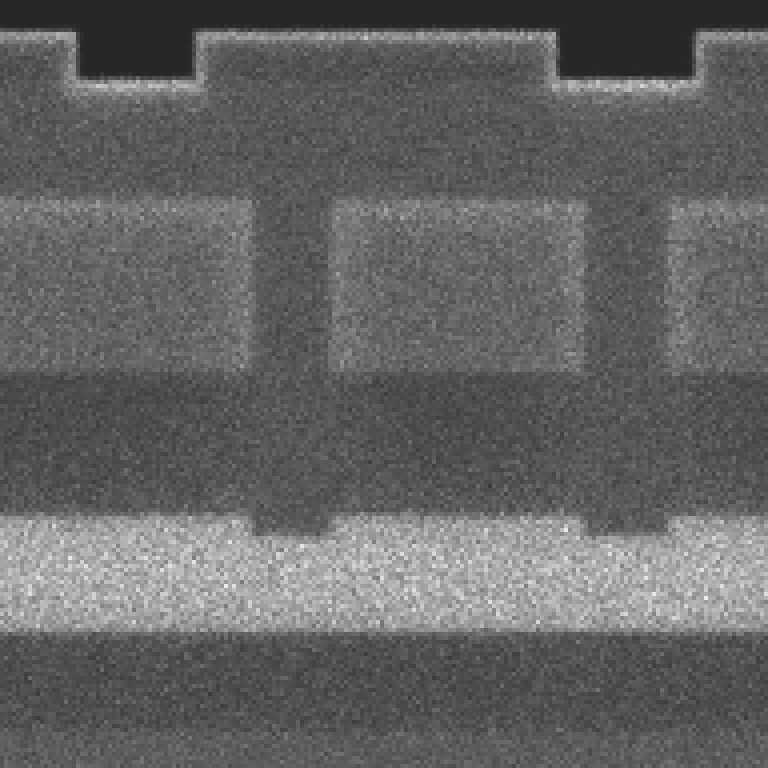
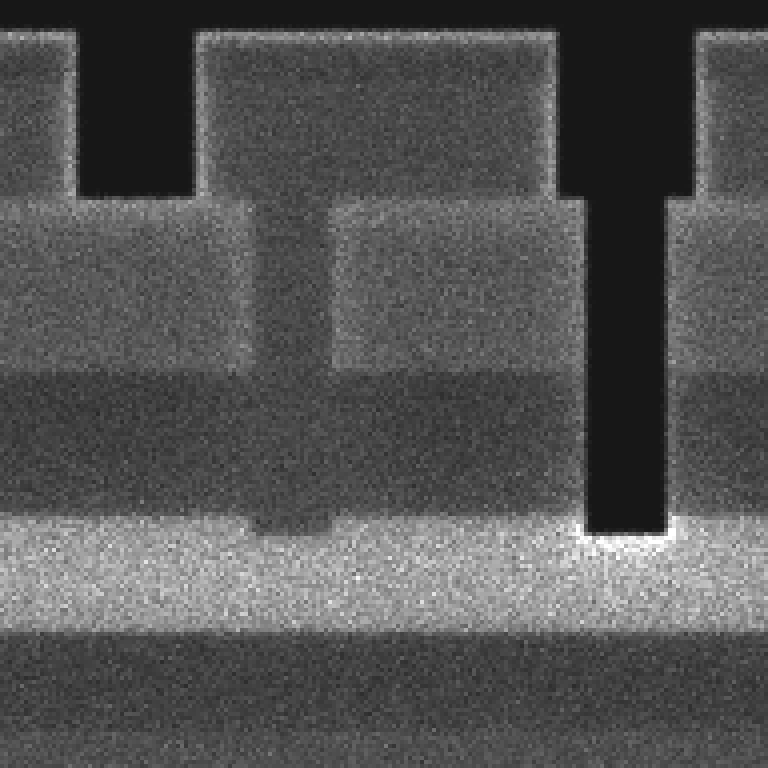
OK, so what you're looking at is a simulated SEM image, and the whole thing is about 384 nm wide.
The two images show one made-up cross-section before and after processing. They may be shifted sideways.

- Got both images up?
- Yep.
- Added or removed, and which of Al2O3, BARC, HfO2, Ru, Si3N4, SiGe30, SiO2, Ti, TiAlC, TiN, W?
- removed, SiO2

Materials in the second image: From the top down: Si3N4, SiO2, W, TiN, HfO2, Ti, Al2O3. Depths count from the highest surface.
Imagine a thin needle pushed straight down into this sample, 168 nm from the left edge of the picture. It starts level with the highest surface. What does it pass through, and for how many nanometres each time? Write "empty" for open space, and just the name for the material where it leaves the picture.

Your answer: Si3N4 24, SiO2 60, W 86, TiN 72, HfO2 58, Ti 50, Al2O3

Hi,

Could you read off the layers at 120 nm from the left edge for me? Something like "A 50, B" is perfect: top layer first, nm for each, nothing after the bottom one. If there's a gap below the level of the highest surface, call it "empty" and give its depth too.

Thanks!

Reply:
Si3N4 24, SiO2 60, W 86, TiN 72, HfO2 58, Ti 50, Al2O3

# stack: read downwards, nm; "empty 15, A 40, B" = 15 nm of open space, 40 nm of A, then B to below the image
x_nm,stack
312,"empty 252, HfO2 48, Ti 50, Al2O3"